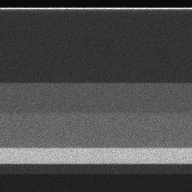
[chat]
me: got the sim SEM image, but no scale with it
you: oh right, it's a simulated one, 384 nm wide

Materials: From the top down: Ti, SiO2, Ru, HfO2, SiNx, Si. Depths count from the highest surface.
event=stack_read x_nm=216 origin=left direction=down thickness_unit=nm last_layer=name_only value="Ti 150, SiO2 60, Ru 70, HfO2 32, SiNx 20, Si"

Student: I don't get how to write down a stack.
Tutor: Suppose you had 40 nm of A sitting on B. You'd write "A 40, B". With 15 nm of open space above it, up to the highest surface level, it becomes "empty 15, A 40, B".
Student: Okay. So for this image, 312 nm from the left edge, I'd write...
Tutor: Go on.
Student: Ti 150, SiO2 60, Ru 70, HfO2 32, SiNx 20, Si